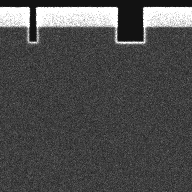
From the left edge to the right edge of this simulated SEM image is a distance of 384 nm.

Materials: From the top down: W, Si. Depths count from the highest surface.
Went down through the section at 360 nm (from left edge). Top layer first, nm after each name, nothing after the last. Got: W 38, Si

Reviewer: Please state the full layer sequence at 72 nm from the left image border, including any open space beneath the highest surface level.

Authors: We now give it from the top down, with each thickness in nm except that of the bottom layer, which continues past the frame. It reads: empty 68, Si